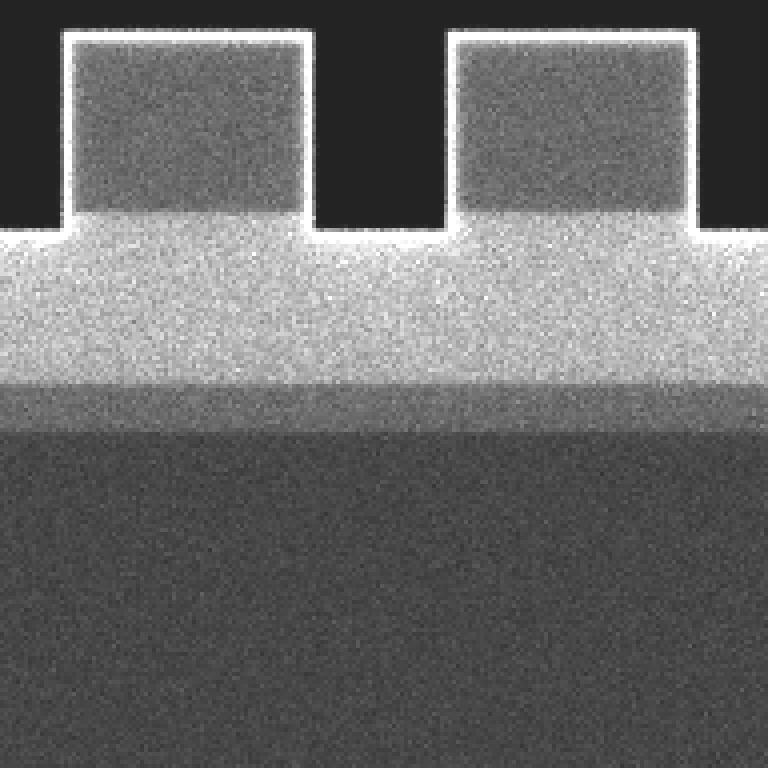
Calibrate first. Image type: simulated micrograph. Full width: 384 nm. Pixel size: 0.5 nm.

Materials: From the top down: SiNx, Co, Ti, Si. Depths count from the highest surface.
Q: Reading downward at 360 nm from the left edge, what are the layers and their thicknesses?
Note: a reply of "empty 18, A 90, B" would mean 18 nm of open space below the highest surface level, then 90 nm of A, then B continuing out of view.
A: empty 100, Co 76, Ti 24, Si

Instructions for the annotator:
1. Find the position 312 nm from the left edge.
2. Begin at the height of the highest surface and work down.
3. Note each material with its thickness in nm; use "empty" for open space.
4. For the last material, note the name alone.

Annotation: SiNx 90, Co 86, Ti 24, Si